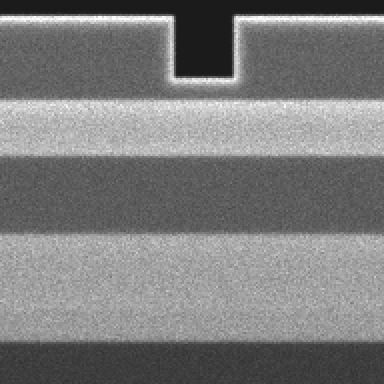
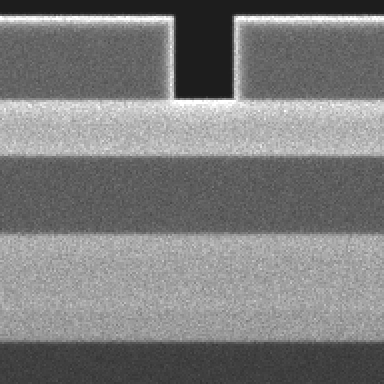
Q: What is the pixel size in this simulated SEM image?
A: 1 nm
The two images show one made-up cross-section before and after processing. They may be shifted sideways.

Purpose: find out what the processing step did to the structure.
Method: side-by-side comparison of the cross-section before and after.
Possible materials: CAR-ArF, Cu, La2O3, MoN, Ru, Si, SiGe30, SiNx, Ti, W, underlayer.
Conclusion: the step removed underlayer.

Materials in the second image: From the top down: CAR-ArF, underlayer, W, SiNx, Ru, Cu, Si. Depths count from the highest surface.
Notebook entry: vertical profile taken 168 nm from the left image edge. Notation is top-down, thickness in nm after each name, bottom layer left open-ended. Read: CAR-ArF 62, underlayer 22, W 56, SiNx 78, Ru 76, Cu 32, Si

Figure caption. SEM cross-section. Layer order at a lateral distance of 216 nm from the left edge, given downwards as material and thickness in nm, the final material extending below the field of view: empty 84, W 56, SiNx 78, Ru 76, Cu 32, Si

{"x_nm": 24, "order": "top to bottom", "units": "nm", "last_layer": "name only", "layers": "CAR-ArF 62, underlayer 22, W 56, SiNx 78, Ru 76, Cu 32, Si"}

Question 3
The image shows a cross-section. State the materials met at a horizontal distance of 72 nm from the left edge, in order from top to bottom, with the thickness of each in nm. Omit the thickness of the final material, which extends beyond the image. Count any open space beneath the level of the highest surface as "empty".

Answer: CAR-ArF 62, underlayer 22, W 56, SiNx 78, Ru 76, Cu 32, Si